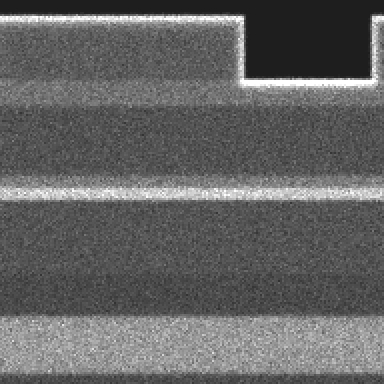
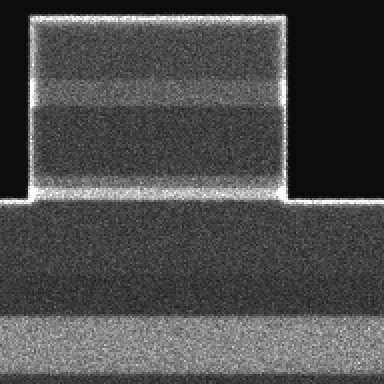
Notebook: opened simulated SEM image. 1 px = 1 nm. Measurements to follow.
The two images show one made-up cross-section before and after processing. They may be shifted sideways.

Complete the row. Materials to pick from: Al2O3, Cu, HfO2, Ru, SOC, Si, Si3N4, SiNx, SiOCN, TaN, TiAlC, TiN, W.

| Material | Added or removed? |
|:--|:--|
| Al2O3 and HfO2 and Ru and TiN | removed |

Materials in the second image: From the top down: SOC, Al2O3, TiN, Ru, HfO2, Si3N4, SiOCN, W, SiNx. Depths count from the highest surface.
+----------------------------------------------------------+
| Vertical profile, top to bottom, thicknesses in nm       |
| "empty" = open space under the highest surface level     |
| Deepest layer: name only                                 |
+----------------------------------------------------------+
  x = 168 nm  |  SOC 64, Al2O3 26, TiN 70, Ru 12, HfO2 12, Si3N4 74, SiOCN 42, W 58, SiNx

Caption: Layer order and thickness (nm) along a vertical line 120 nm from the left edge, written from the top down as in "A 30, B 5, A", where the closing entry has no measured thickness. SOC 64, Al2O3 26, TiN 70, Ru 12, HfO2 12, Si3N4 74, SiOCN 42, W 58, SiNx